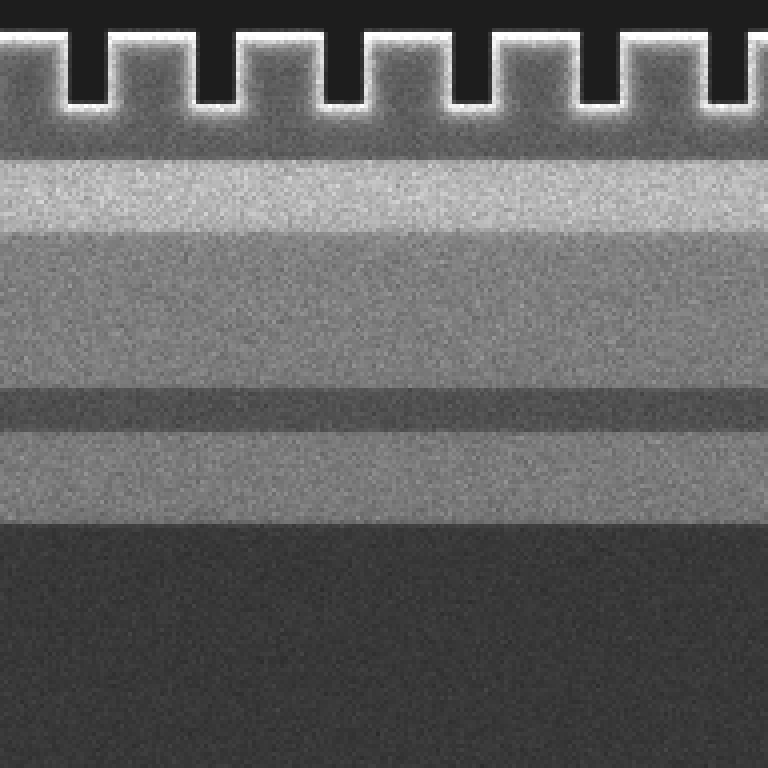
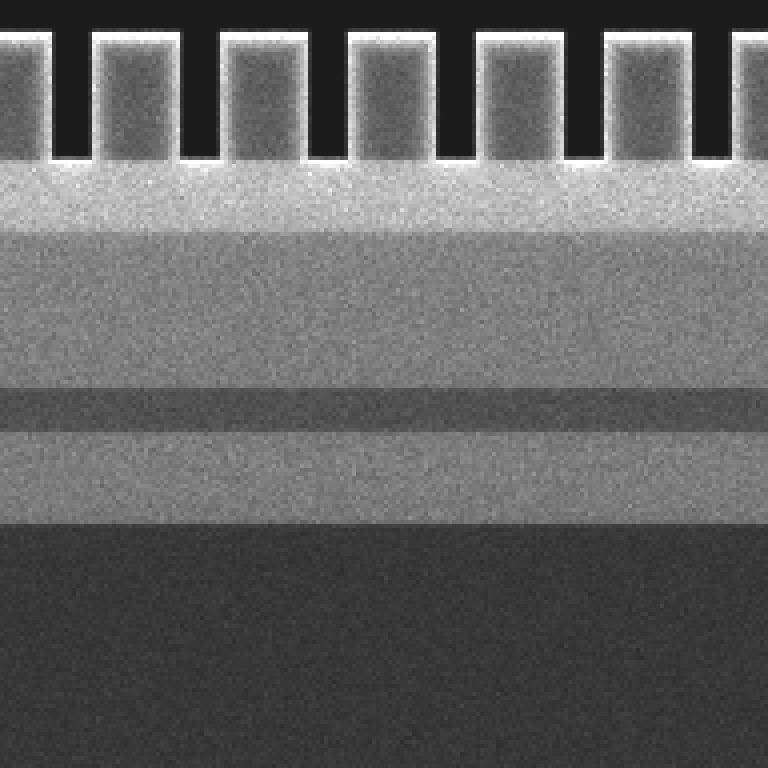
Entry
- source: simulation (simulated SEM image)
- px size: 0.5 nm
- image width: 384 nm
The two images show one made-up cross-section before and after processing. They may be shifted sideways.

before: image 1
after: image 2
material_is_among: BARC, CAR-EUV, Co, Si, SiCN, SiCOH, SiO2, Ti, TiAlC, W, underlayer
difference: underlayer, removed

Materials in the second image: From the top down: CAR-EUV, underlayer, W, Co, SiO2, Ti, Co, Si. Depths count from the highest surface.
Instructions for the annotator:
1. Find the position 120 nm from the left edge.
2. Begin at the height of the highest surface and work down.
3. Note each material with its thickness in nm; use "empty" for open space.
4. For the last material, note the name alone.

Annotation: CAR-EUV 36, underlayer 28, W 36, Co 68, SiO2 10, Ti 22, Co 46, Si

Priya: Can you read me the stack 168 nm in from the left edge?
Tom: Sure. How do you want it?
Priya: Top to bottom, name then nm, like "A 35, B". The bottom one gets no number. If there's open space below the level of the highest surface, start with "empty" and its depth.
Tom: empty 64, W 36, Co 68, SiO2 10, Ti 22, Co 46, Si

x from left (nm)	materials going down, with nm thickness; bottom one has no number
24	CAR-EUV 36, underlayer 28, W 36, Co 68, SiO2 10, Ti 22, Co 46, Si